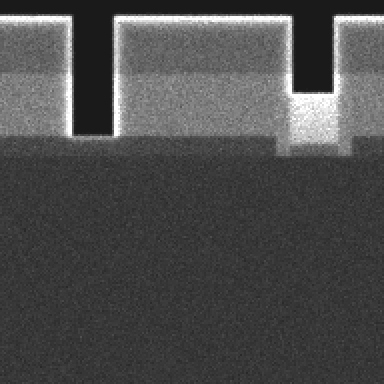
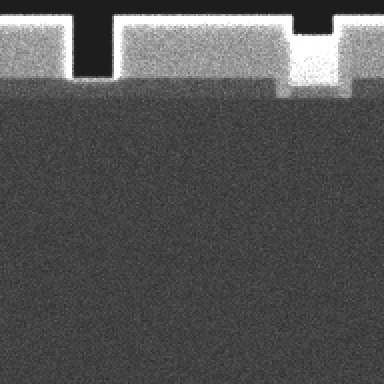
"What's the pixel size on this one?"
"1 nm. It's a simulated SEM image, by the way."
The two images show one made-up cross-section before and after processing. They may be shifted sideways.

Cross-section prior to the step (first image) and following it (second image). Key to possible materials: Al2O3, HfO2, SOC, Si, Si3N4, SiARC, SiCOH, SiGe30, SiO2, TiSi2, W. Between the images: SOC was removed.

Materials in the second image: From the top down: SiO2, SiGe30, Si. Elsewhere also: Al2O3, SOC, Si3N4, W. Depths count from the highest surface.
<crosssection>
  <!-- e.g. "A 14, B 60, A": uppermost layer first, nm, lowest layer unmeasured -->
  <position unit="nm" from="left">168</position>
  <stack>SiO2 62, SiGe30 20, Si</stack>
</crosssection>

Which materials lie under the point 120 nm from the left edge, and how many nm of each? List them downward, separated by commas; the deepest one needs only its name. SiO2 62, SiGe30 20, Si